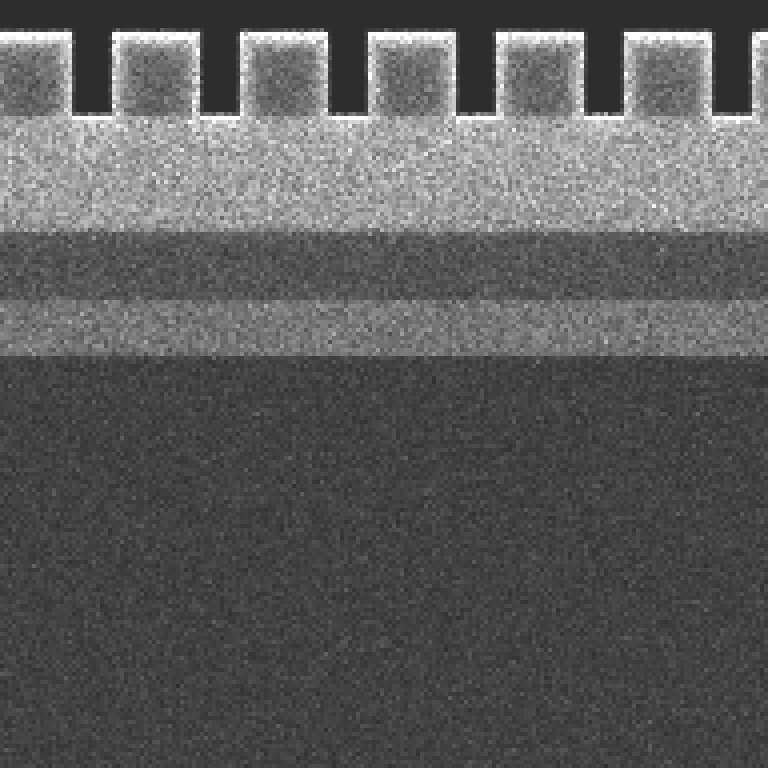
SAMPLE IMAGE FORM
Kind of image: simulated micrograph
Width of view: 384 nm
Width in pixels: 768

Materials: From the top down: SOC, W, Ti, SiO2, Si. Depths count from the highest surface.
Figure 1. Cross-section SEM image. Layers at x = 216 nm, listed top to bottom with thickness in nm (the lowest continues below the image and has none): SOC 42, W 58, Ti 34, SiO2 28, Si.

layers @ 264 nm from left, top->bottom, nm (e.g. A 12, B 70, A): SOC 42, W 58, Ti 34, SiO2 28, Si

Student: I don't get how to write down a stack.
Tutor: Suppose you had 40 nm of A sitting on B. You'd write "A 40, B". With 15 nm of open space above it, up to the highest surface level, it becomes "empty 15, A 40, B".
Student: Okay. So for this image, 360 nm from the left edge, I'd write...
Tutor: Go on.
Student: empty 42, W 58, Ti 34, SiO2 28, Si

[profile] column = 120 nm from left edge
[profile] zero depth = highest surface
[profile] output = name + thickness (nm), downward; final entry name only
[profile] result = SOC 42, W 58, Ti 34, SiO2 28, Si